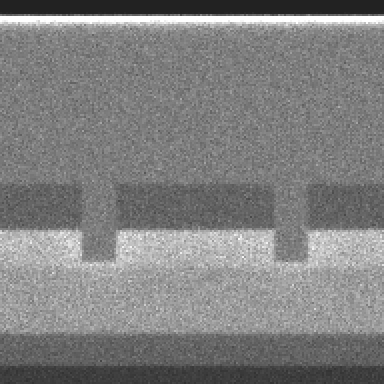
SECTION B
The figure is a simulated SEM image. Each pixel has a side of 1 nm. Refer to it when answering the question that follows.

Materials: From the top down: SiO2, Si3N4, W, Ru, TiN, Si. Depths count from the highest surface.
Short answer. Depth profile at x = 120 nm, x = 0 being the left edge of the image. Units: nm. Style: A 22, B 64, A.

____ SiO2 168, Si3N4 46, W 38, Ru 66, TiN 32, Si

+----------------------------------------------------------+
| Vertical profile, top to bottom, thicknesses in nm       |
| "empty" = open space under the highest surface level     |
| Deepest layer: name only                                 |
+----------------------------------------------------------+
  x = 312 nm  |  SiO2 168, Si3N4 46, W 38, Ru 66, TiN 32, Si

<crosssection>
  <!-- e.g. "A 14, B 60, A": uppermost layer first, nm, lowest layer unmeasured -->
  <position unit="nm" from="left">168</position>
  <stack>SiO2 168, Si3N4 46, W 38, Ru 66, TiN 32, Si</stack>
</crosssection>